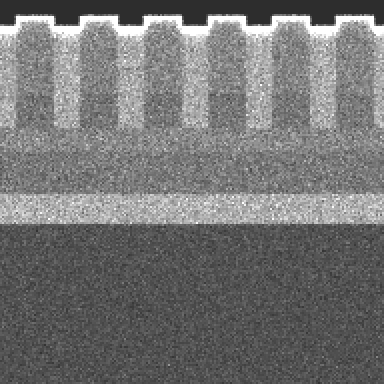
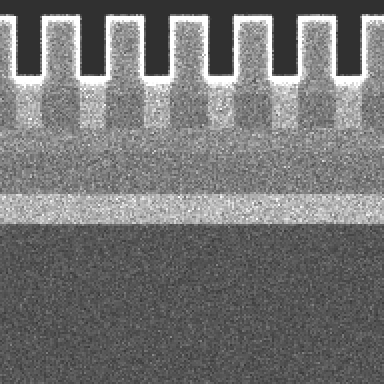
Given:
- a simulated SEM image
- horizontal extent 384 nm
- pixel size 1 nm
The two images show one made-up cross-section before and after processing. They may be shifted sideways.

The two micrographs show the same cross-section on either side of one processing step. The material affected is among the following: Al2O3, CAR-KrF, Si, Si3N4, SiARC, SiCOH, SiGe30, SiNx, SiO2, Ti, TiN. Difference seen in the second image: SiO2 removed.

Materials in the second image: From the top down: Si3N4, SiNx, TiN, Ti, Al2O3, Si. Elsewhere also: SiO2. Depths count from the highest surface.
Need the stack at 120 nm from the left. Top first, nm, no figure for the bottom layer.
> Si3N4 78, SiNx 34, TiN 24, Ti 42, Al2O3 30, Si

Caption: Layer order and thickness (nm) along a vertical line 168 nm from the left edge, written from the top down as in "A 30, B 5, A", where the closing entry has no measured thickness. empty 60, SiO2 52, TiN 24, Ti 42, Al2O3 30, Si